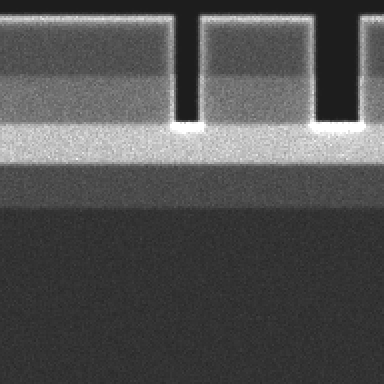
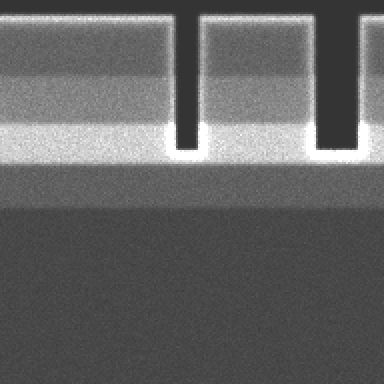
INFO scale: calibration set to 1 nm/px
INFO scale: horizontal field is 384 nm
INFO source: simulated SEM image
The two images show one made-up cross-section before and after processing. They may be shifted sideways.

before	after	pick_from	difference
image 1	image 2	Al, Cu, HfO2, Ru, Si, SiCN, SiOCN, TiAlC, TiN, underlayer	HfO2 removed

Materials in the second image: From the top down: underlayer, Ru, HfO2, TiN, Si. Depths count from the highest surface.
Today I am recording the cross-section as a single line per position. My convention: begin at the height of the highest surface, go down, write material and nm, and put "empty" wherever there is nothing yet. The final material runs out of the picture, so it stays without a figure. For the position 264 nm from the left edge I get underlayer 60, Ru 48, HfO2 40, TiN 44, Si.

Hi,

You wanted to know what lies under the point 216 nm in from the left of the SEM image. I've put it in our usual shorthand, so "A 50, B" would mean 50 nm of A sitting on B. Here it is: underlayer 60, Ru 48, HfO2 40, TiN 44, Si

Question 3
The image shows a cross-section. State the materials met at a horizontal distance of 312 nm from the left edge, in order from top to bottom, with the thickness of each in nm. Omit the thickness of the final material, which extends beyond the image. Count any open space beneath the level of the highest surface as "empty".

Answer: underlayer 60, Ru 48, HfO2 40, TiN 44, Si